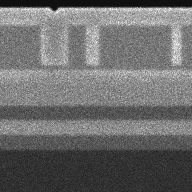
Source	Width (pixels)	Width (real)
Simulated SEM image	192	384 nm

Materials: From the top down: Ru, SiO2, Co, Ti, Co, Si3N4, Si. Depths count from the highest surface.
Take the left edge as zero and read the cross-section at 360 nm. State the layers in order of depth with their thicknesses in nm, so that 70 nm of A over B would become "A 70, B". Ru 114, SiO2 10, Co 72, Ti 28, Co 30, Si3N4 30, Si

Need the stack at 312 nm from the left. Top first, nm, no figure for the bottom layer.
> Ru 34, SiO2 90, Co 72, Ti 28, Co 30, Si3N4 30, Si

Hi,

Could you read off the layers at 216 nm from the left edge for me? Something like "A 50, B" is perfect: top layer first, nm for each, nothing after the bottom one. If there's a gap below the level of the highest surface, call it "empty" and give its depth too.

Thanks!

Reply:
Ru 34, SiO2 90, Co 72, Ti 28, Co 30, Si3N4 30, Si